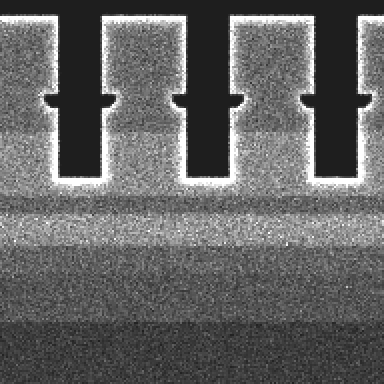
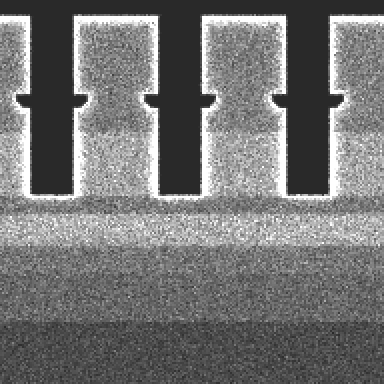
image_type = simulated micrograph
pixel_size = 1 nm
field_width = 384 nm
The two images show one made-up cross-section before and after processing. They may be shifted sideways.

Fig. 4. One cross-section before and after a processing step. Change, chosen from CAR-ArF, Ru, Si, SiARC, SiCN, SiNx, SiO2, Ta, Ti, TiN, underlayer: SiO2 removed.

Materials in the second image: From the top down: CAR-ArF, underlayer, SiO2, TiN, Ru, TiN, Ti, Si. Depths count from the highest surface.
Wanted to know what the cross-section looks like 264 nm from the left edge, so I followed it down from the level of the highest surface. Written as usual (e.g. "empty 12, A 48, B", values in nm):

CAR-ArF 78, underlayer 38, SiO2 64, TiN 18, Ru 32, TiN 28, Ti 48, Si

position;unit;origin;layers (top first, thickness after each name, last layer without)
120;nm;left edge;CAR-ArF 78, underlayer 38, SiO2 64, TiN 18, Ru 32, TiN 28, Ti 48, Si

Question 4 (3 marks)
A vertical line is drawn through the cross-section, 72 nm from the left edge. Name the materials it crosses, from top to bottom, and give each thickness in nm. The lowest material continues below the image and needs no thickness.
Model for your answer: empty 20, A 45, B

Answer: empty 180, TiN 18, Ru 32, TiN 28, Ti 48, Si